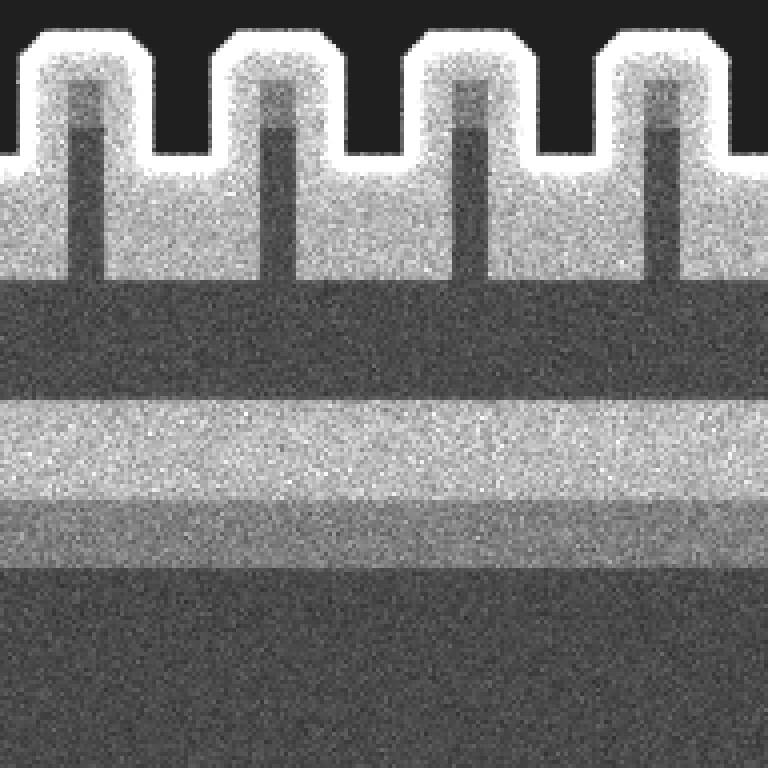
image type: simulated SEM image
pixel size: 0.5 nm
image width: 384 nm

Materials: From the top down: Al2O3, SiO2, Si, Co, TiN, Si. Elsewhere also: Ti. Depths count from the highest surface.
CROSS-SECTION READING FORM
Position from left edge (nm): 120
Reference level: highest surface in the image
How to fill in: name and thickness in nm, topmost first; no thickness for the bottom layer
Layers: Al2O3 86, SiO2 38, Si 60, Co 50, TiN 34, Si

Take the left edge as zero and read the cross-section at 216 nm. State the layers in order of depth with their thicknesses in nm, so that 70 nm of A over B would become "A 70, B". Al2O3 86, SiO2 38, Si 60, Co 50, TiN 34, Si